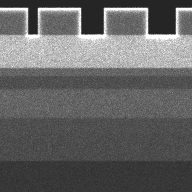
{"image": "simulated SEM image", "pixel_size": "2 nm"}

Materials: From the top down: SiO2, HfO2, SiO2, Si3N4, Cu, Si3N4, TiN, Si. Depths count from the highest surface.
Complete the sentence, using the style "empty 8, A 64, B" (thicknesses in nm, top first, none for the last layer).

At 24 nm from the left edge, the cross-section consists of SiO2 54, HfO2 66, SiO2 16, Si3N4 26, Cu 58, Si3N4 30, TiN 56, Si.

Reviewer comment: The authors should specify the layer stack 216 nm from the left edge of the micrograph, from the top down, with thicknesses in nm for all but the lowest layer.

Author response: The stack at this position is SiO2 54, HfO2 66, SiO2 16, Si3N4 26, Cu 58, Si3N4 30, TiN 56, Si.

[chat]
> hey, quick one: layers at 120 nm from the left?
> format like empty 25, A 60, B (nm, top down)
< SiO2 54, HfO2 66, SiO2 16, Si3N4 26, Cu 58, Si3N4 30, TiN 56, Si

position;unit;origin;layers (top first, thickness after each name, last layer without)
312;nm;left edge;empty 54, HfO2 66, SiO2 16, Si3N4 26, Cu 58, Si3N4 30, TiN 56, Si